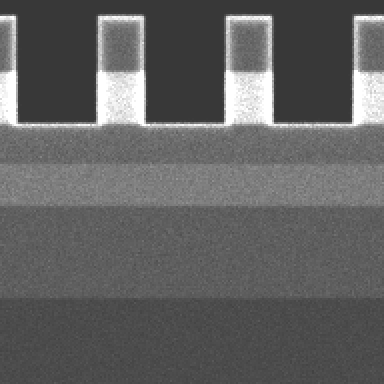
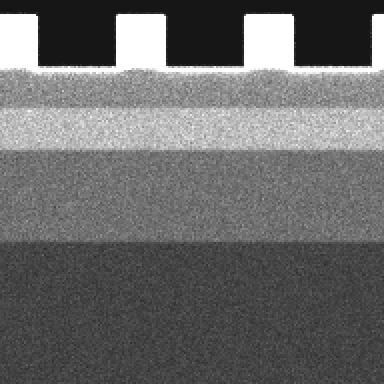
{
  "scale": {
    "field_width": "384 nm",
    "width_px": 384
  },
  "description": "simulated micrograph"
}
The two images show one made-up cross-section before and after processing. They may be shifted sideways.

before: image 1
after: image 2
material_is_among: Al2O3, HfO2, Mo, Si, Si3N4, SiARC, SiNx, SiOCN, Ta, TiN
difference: SiARC, removed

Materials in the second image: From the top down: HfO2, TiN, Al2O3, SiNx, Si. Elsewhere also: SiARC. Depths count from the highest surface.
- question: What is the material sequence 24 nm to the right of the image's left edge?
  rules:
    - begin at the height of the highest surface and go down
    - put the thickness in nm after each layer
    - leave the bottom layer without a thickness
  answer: HfO2 52, TiN 40, Al2O3 42, SiNx 92, Si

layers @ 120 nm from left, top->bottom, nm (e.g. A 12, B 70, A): HfO2 52, TiN 40, Al2O3 42, SiNx 92, Si